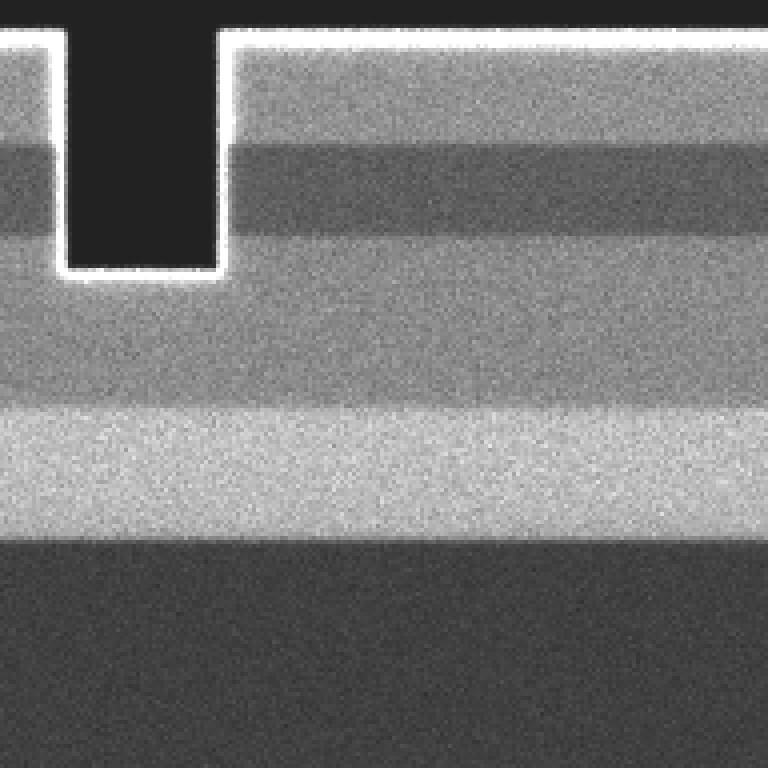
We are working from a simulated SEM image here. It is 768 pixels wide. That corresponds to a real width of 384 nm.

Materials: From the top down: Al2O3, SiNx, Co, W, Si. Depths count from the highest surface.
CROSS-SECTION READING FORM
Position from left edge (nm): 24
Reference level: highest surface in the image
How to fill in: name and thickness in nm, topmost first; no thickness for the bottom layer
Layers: Al2O3 56, SiNx 46, Co 86, W 66, Si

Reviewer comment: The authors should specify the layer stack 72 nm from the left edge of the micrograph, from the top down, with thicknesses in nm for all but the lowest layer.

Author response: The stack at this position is empty 120, Co 68, W 66, Si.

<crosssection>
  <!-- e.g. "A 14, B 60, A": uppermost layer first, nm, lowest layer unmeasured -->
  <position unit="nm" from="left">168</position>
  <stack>Al2O3 56, SiNx 46, Co 86, W 66, Si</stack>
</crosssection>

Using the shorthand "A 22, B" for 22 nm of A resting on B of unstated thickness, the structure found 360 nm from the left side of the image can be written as Al2O3 56, SiNx 46, Co 86, W 66, Si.